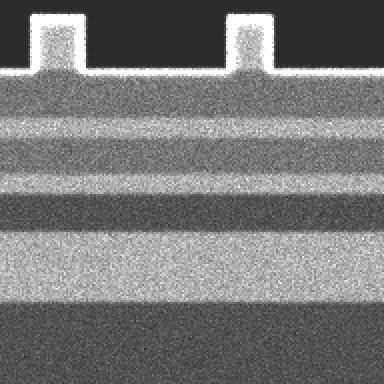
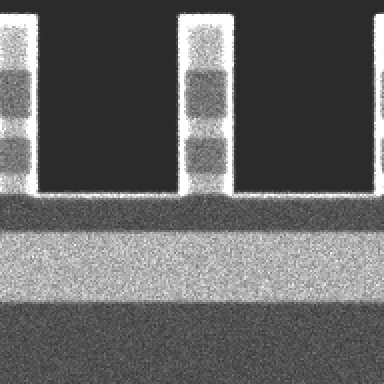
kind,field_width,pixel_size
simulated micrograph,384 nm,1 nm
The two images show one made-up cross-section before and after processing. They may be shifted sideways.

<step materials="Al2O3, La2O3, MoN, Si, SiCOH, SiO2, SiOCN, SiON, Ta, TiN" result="removed SiO2 and SiOCN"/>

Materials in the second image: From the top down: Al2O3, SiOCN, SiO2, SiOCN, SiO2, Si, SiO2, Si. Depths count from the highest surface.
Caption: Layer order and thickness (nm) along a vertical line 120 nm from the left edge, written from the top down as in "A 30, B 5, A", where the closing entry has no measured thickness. empty 178, Si 38, SiO2 70, Si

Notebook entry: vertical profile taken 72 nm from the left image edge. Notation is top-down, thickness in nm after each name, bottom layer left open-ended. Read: empty 178, Si 38, SiO2 70, Si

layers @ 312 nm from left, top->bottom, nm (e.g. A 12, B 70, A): empty 178, Si 38, SiO2 70, Si